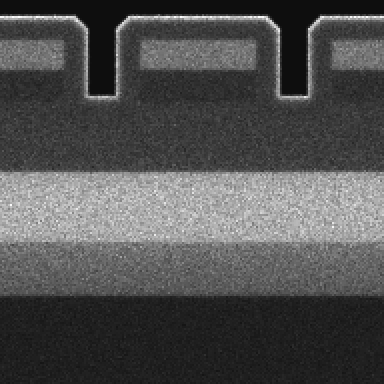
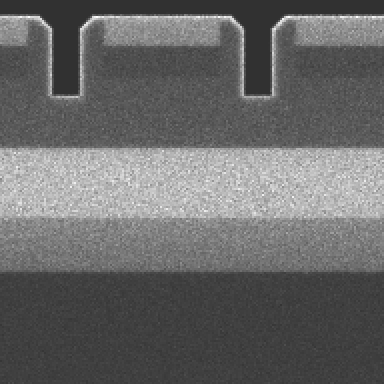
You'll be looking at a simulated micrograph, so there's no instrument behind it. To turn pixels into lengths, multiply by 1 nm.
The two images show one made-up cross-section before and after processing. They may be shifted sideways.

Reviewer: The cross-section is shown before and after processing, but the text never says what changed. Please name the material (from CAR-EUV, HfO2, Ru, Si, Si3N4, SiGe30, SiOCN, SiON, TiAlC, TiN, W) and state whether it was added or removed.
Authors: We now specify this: Si3N4, removed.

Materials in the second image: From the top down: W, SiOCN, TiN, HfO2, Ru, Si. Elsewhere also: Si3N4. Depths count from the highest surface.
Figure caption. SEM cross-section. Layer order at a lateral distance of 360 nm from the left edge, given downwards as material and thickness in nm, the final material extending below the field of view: W 30, SiOCN 32, TiN 70, HfO2 70, Ru 54, Si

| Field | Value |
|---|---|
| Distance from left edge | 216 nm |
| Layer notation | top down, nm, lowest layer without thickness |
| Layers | W 30, SiOCN 32, TiN 70, HfO2 70, Ru 54, Si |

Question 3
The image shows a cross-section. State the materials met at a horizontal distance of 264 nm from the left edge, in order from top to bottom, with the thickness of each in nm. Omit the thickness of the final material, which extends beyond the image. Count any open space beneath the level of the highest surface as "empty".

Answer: empty 80, TiN 52, HfO2 70, Ru 54, Si